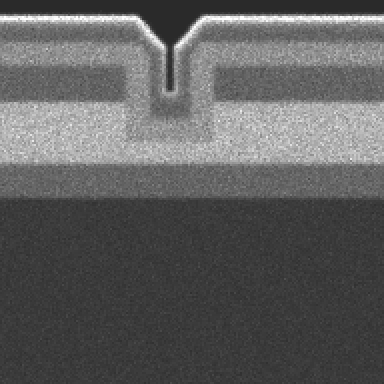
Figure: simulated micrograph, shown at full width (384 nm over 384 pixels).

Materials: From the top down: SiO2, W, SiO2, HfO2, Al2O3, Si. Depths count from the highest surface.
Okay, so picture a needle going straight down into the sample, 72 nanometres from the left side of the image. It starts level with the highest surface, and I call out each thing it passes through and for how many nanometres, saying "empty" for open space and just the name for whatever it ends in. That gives SiO2 26, W 24, SiO2 36, HfO2 62, Al2O3 34, Si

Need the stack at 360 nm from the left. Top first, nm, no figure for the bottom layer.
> SiO2 26, W 24, SiO2 36, HfO2 62, Al2O3 34, Si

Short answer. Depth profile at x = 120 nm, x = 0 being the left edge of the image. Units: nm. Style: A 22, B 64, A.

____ SiO2 26, W 24, SiO2 36, HfO2 62, Al2O3 34, Si